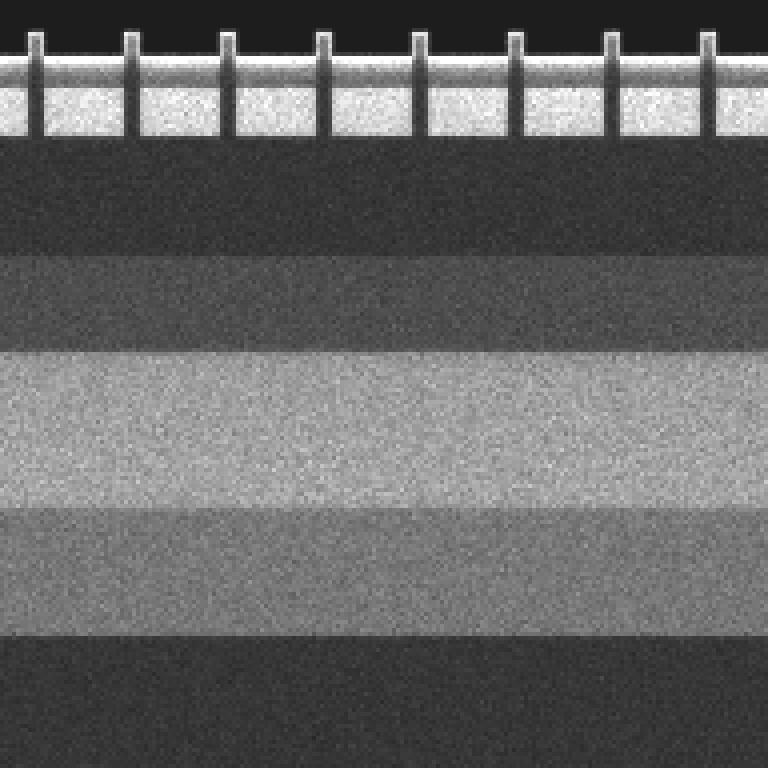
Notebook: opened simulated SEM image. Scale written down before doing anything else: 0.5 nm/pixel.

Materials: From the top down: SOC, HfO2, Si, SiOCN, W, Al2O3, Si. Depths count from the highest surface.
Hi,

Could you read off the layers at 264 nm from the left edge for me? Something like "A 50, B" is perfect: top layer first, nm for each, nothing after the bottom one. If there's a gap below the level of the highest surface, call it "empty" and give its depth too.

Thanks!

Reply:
empty 12, SOC 16, HfO2 24, Si 60, SiOCN 48, W 78, Al2O3 64, Si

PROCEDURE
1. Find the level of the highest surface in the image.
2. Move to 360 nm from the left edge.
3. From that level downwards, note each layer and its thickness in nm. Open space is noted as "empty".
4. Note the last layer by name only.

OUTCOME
empty 12, SOC 16, HfO2 24, Si 60, SiOCN 48, W 78, Al2O3 64, Si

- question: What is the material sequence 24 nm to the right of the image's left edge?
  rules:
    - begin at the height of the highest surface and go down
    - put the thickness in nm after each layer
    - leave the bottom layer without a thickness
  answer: empty 12, SOC 16, HfO2 24, Si 60, SiOCN 48, W 78, Al2O3 64, Si